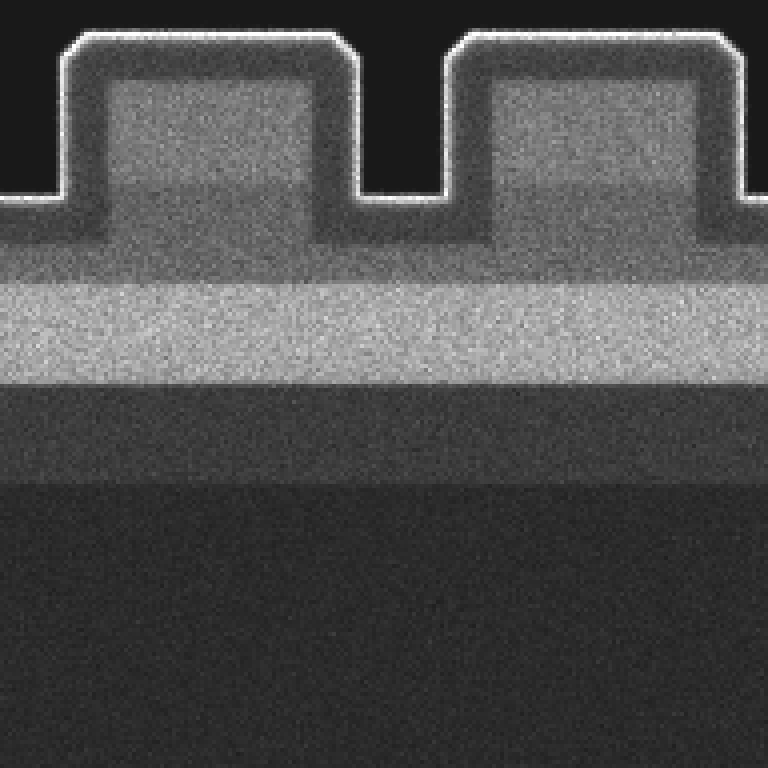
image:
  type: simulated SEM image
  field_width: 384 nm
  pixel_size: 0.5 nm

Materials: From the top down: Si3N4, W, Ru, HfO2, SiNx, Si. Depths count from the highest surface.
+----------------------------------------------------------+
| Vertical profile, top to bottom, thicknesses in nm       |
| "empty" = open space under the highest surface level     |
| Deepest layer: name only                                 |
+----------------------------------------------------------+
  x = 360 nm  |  empty 2, Si3N4 104, Ru 20, HfO2 50, SiNx 50, Si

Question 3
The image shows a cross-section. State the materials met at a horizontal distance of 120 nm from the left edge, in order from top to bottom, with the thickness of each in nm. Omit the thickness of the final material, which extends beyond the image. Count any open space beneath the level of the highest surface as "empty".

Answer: Si3N4 24, W 52, Ru 50, HfO2 50, SiNx 50, Si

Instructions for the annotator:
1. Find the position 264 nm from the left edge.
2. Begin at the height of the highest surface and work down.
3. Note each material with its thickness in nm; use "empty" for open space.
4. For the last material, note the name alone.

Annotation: Si3N4 24, W 52, Ru 50, HfO2 50, SiNx 50, Si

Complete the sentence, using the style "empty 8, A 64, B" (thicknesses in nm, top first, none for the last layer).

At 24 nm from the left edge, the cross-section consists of empty 82, Si3N4 24, Ru 20, HfO2 50, SiNx 50, Si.